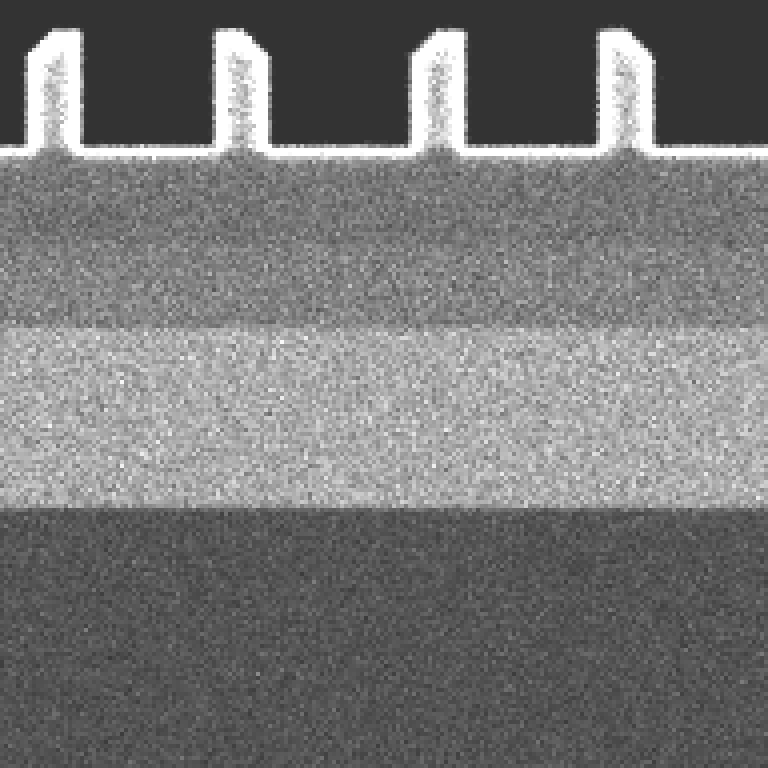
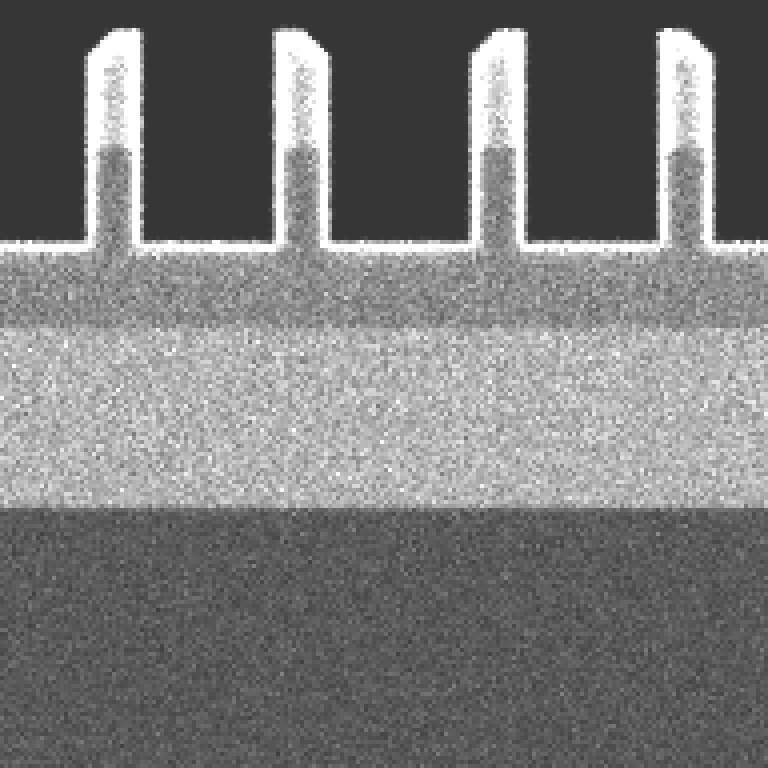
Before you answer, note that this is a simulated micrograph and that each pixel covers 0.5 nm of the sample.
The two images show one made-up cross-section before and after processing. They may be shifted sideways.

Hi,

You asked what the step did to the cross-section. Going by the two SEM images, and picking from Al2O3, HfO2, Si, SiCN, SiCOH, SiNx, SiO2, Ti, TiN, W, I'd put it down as SiNx, removed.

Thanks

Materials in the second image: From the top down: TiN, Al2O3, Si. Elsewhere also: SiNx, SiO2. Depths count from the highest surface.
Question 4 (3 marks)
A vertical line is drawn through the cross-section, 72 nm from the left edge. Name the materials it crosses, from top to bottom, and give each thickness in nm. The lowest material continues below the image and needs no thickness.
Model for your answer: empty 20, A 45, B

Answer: empty 106, TiN 42, Al2O3 90, Si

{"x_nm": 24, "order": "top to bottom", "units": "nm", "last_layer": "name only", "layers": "empty 106, TiN 42, Al2O3 90, Si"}